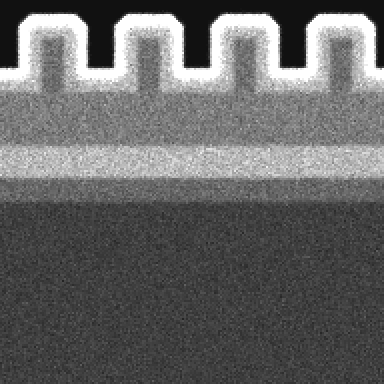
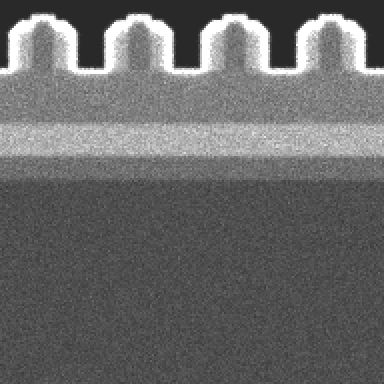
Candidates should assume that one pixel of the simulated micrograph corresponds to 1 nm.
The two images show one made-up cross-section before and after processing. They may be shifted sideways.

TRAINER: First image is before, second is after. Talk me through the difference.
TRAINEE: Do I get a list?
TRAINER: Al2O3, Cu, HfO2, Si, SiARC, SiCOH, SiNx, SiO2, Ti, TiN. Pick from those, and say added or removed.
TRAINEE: removed: SiO2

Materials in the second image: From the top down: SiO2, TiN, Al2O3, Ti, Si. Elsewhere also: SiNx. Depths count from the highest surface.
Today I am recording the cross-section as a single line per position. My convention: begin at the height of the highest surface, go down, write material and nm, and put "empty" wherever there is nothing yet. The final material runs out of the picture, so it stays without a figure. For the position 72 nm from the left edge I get empty 14, SiO2 40, TiN 54, Al2O3 32, Ti 24, Si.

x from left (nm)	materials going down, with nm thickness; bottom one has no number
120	empty 6, SiO2 48, TiN 54, Al2O3 32, Ti 24, Si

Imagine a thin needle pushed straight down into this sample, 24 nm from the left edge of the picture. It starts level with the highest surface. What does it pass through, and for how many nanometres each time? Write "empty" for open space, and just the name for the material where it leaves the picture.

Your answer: empty 6, SiO2 48, TiN 54, Al2O3 32, Ti 24, Si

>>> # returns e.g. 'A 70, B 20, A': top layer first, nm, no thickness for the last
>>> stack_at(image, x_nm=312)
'empty 6, SiO2 48, TiN 54, Al2O3 32, Ti 24, Si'